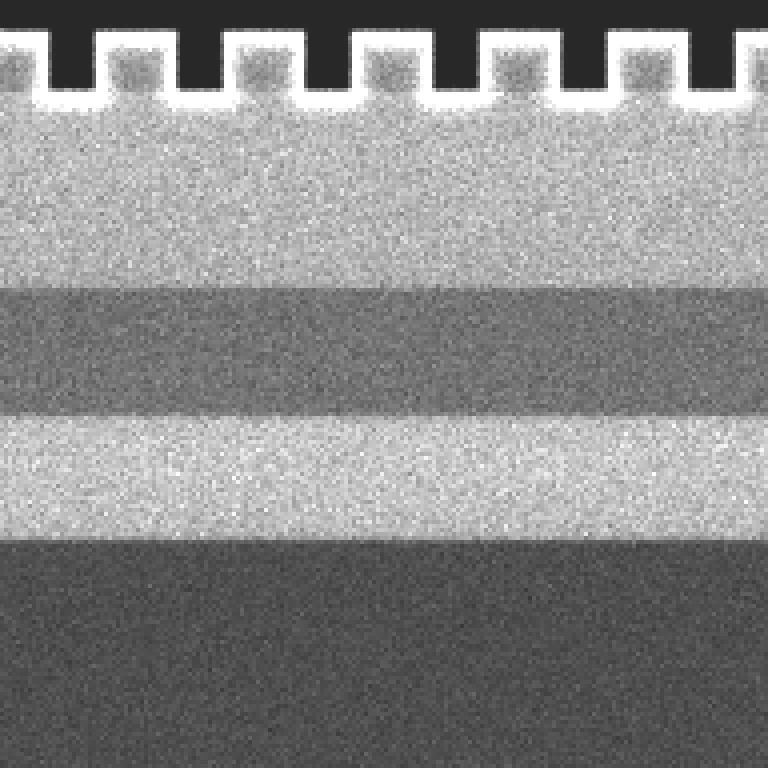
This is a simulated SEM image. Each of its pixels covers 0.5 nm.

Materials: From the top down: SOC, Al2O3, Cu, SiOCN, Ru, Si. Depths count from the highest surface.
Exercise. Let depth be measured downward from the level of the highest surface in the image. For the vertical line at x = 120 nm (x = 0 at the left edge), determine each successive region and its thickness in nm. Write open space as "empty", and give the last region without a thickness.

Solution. SOC 30, Al2O3 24, Cu 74, SiOCN 64, Ru 62, Si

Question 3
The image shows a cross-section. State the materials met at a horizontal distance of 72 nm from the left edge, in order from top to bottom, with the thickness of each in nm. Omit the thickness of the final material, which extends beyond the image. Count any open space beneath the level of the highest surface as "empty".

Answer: SOC 30, Al2O3 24, Cu 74, SiOCN 64, Ru 62, Si